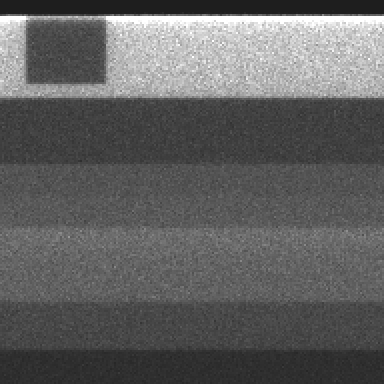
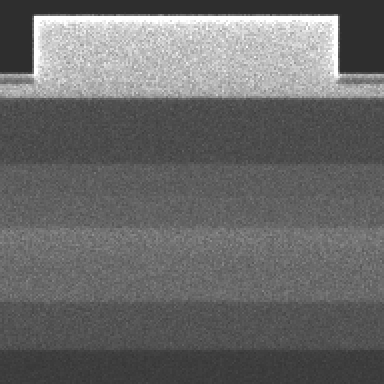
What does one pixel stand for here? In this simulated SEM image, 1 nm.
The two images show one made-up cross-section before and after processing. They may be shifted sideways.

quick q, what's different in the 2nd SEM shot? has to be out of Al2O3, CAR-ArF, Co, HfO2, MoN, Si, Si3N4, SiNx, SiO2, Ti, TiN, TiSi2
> Si3N4 removed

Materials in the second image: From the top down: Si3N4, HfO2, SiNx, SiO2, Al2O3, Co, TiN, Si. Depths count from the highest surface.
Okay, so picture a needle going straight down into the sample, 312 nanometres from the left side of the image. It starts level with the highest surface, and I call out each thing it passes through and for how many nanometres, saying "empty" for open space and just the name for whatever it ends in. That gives HfO2 82, SiNx 66, SiO2 32, Al2O3 32, Co 74, TiN 48, Si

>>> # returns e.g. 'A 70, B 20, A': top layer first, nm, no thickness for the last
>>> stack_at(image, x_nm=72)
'HfO2 82, SiNx 66, SiO2 32, Al2O3 32, Co 74, TiN 48, Si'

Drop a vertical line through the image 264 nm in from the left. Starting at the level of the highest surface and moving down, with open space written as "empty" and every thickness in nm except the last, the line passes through HfO2 82, SiNx 66, SiO2 32, Al2O3 32, Co 74, TiN 48, Si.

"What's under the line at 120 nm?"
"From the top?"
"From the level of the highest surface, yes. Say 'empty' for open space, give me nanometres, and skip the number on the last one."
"HfO2 82, SiNx 66, SiO2 32, Al2O3 32, Co 74, TiN 48, Si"